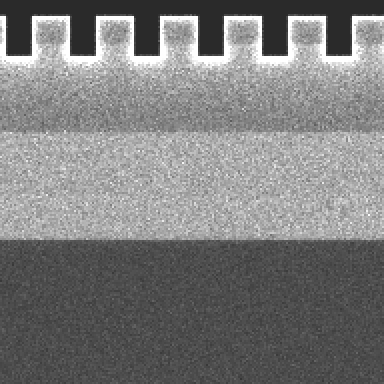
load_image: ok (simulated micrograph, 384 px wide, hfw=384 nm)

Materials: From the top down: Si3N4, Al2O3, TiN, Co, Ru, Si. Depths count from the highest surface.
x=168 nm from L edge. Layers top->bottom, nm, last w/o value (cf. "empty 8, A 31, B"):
Si3N4 28, Al2O3 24, TiN 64, Co 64, Ru 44, Si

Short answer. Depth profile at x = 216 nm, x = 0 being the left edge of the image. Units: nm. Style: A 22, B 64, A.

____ empty 40, Al2O3 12, TiN 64, Co 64, Ru 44, Si